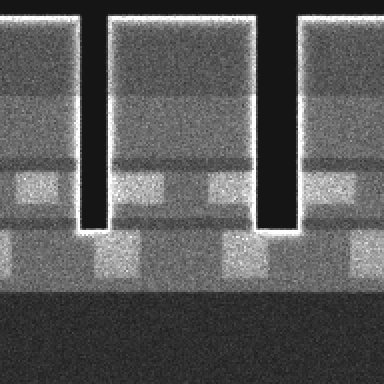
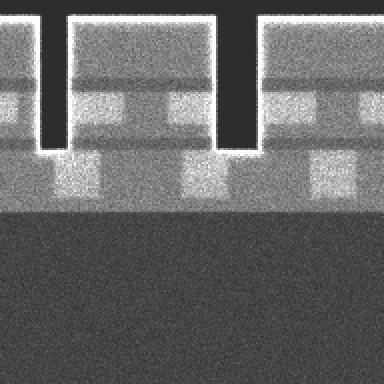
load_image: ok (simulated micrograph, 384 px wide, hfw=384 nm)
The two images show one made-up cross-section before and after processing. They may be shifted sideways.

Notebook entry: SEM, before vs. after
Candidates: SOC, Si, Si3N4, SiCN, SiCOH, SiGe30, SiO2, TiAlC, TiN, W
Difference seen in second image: SOC removed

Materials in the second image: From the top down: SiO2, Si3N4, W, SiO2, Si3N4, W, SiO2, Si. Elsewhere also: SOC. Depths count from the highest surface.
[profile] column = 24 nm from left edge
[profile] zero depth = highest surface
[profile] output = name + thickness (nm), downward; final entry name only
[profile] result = SiO2 62, Si3N4 14, SiO2 46, Si3N4 12, SiO2 62, Si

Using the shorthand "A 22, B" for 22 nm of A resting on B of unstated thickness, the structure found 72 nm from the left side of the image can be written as SiO2 62, Si3N4 14, SiO2 46, Si3N4 12, W 48, SiO2 14, Si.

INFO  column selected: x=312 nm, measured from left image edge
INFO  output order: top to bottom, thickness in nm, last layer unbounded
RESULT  SiO2 62, Si3N4 14, W 32, SiO2 14, Si3N4 12, W 48, SiO2 14, Si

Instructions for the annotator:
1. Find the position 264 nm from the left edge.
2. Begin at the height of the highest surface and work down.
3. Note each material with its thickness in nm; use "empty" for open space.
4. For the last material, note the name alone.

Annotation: SiO2 62, Si3N4 14, SiO2 46, Si3N4 12, SiO2 62, Si